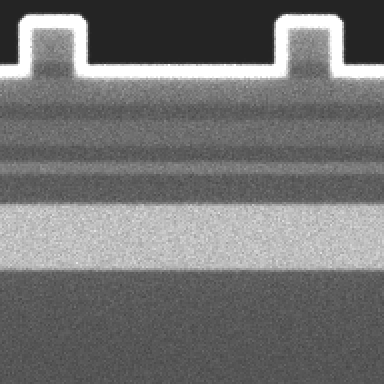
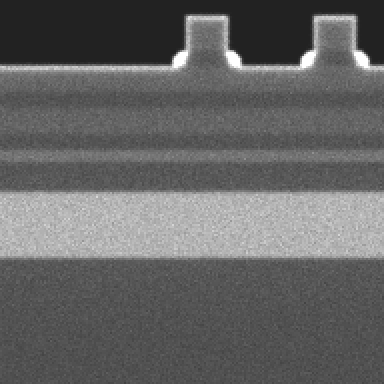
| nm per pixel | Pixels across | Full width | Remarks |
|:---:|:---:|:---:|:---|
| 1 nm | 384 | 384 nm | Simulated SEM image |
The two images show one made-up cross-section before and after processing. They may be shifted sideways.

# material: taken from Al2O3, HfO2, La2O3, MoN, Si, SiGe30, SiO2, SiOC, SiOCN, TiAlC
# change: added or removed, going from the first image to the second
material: Al2O3
change: removed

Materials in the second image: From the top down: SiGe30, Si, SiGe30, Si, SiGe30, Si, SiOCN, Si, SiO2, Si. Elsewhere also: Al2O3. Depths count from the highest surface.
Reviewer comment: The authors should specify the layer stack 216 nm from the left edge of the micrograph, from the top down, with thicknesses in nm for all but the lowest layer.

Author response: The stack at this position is SiGe30 34, Si 16, SiGe30 26, Si 16, SiGe30 26, Si 16, SiOCN 12, Si 30, SiO2 66, Si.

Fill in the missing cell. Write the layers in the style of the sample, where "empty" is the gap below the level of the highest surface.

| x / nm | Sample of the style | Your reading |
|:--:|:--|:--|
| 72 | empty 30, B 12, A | empty 50, SiGe30 26, Si 16, SiGe30 26, Si 16, SiOCN 12, Si 30, SiO2 66, Si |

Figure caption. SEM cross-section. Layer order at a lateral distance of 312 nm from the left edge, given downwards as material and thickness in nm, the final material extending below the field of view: empty 36, Al2O3 14, SiGe30 26, Si 16, SiGe30 26, Si 16, SiOCN 12, Si 30, SiO2 66, Si